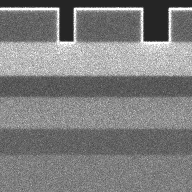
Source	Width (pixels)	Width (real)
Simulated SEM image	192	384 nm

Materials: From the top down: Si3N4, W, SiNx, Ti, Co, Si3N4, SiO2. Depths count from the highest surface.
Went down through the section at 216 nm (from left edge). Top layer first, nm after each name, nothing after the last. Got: Si3N4 68, W 68, SiNx 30, Ti 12, Co 64, Si3N4 52, SiO2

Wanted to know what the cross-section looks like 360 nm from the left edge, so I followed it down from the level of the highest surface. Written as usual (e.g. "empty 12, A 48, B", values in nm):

Si3N4 68, W 68, SiNx 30, Ti 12, Co 64, Si3N4 52, SiO2